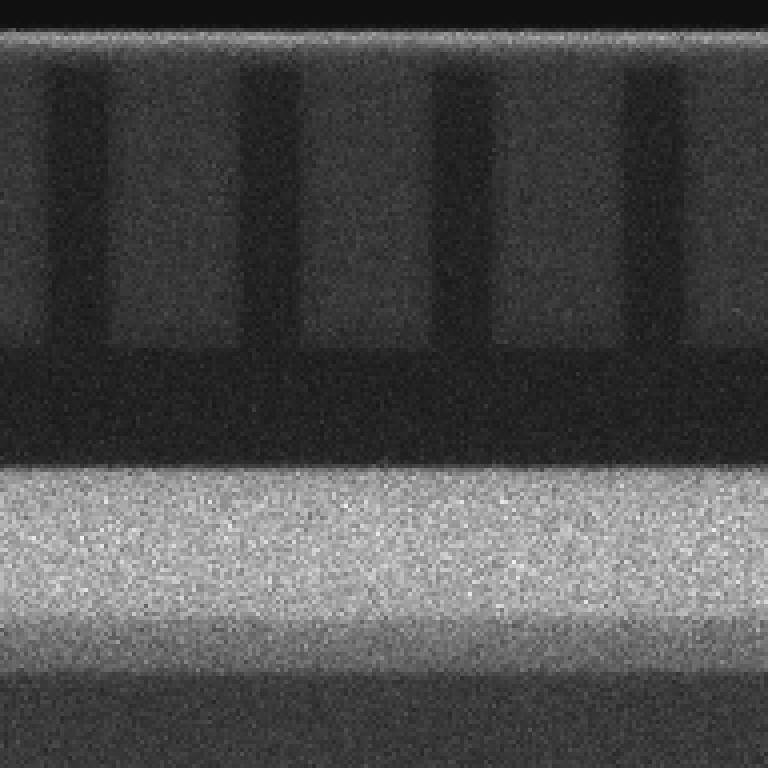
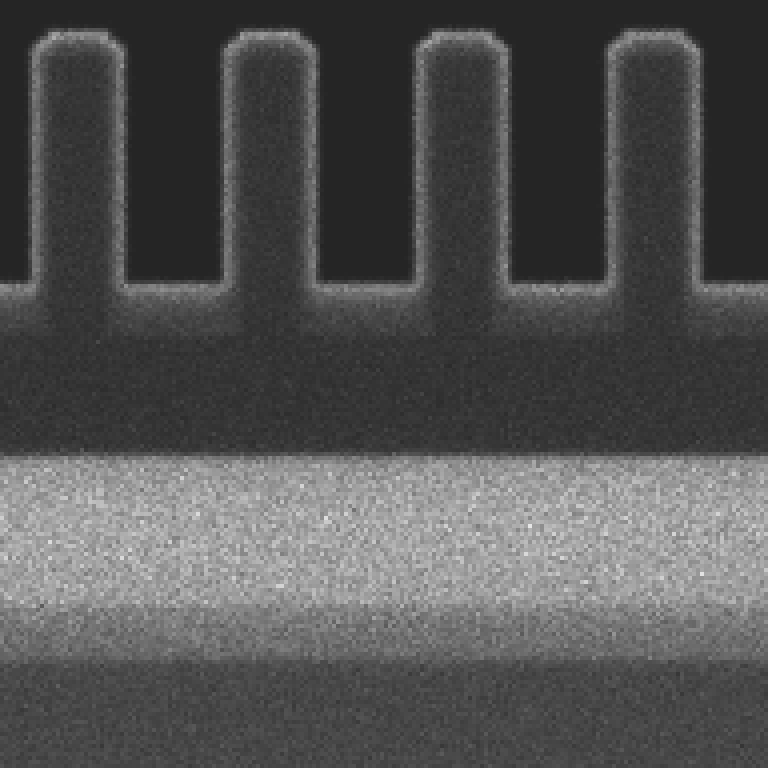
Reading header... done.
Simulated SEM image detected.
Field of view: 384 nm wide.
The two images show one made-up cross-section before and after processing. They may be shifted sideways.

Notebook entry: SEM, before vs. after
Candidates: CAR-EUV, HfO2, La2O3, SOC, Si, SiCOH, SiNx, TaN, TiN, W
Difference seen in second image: SOC removed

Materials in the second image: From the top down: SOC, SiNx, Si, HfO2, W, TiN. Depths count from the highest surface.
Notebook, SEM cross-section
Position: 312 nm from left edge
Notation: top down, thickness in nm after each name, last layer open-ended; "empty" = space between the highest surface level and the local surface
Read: SiNx 12, Si 200, HfO2 74, W 28, TiN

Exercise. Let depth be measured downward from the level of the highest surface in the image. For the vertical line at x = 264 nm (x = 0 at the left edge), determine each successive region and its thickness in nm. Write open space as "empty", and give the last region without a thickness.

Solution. empty 126, SOC 14, SiNx 12, Si 60, HfO2 74, W 28, TiN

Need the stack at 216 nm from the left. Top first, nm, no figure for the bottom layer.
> SiNx 12, Si 200, HfO2 74, W 28, TiN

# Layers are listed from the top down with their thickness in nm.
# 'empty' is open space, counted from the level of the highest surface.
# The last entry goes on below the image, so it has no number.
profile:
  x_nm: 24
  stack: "SiNx 12, Si 200, HfO2 74, W 28, TiN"